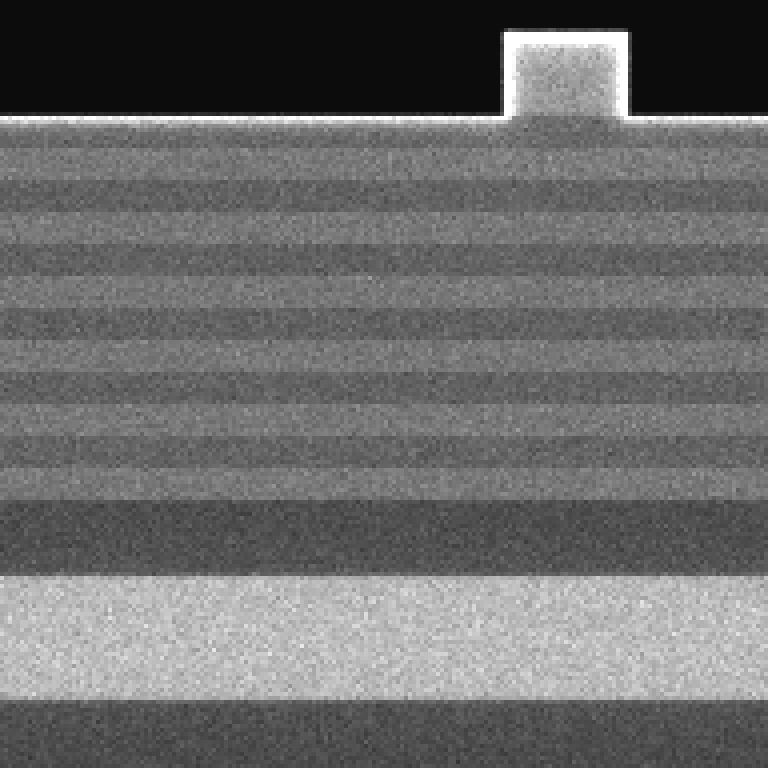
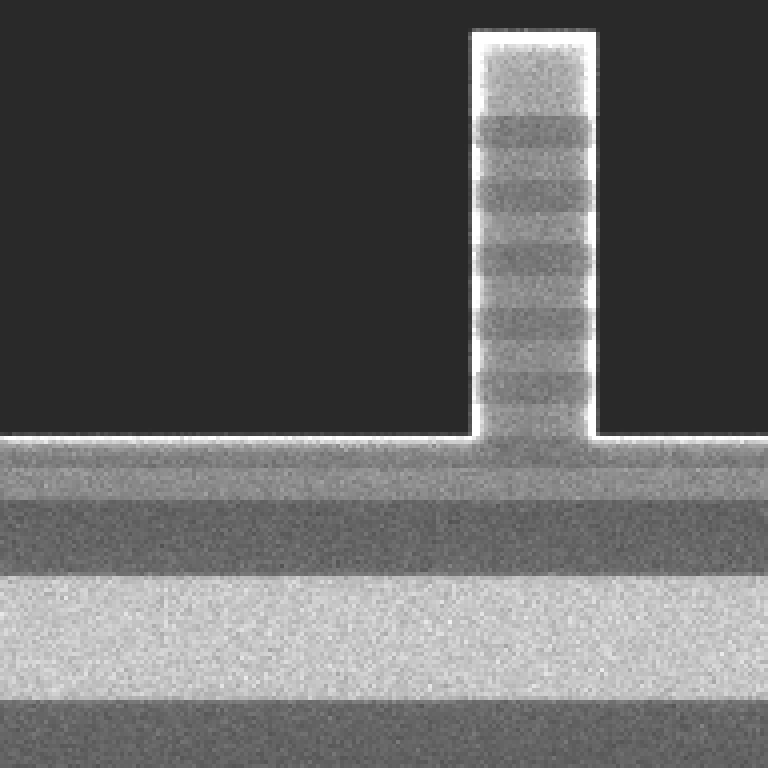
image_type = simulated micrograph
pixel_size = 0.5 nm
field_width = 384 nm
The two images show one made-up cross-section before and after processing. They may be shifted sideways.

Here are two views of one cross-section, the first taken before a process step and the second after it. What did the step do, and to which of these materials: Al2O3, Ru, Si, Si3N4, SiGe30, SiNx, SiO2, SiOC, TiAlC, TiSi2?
It removed SiGe30 and SiNx.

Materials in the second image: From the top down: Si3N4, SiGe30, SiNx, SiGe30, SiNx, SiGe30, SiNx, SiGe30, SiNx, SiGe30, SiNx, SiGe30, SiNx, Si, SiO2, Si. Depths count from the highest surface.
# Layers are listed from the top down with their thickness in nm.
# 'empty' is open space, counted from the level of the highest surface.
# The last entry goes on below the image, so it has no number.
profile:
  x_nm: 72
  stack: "empty 202, SiGe30 16, SiNx 16, Si 38, SiO2 62, Si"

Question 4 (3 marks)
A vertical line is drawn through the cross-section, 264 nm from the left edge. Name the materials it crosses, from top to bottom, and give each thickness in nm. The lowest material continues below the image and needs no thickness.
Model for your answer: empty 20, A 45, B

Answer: Si3N4 42, SiGe30 16, SiNx 16, SiGe30 16, SiNx 16, SiGe30 16, SiNx 16, SiGe30 16, SiNx 16, SiGe30 16, SiNx 16, SiGe30 16, SiNx 16, Si 38, SiO2 62, Si